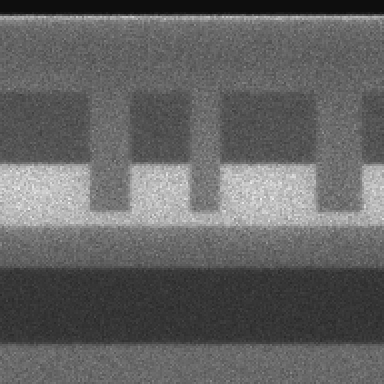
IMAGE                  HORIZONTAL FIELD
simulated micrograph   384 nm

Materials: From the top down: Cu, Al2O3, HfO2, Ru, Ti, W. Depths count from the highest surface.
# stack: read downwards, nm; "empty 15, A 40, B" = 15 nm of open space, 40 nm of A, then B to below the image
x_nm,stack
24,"Cu 76, Al2O3 72, HfO2 62, Ru 42, Ti 76, W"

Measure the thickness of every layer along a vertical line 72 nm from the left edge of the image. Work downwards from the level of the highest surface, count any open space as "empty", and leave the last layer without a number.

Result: Cu 76, Al2O3 72, HfO2 62, Ru 42, Ti 76, W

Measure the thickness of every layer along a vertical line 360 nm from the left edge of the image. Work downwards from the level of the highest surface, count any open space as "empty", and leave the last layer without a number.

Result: Cu 196, HfO2 14, Ru 42, Ti 76, W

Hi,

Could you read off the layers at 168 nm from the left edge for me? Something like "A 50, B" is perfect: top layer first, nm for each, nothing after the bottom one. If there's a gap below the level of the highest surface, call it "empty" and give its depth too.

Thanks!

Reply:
Cu 76, Al2O3 72, HfO2 62, Ru 42, Ti 76, W